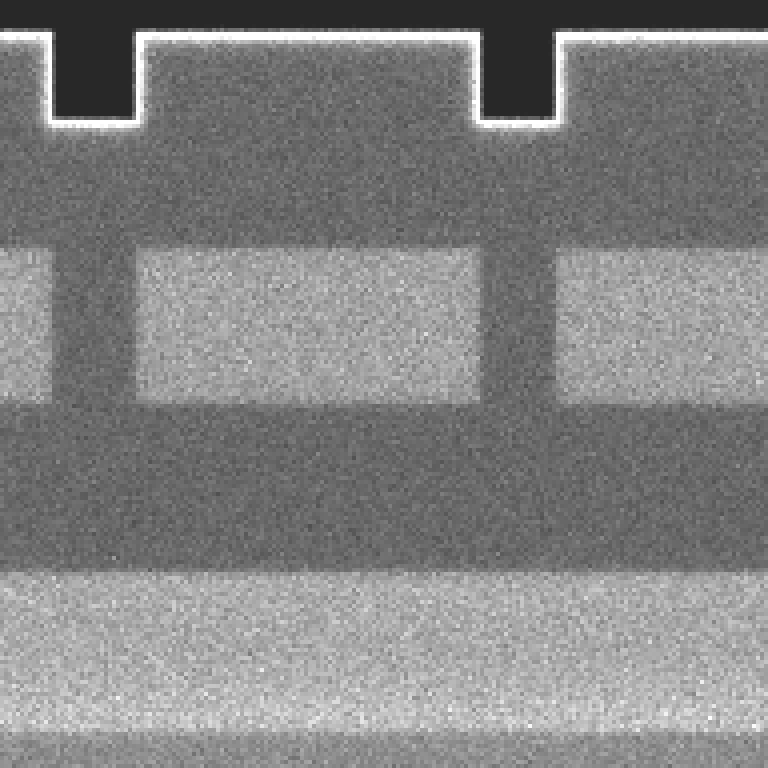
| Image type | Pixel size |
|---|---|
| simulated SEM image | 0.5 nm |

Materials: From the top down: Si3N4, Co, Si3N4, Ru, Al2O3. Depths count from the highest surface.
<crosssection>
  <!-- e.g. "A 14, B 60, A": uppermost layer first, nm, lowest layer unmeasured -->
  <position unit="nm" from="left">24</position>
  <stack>Si3N4 108, Co 78, Si3N4 84, Ru 80, Al2O3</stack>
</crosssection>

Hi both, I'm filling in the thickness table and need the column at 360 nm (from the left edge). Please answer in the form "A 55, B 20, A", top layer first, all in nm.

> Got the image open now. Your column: Si3N4 108, Co 78, Si3N4 84, Ru 80, Al2O3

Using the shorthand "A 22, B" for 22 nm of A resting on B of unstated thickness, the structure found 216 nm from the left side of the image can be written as Si3N4 108, Co 78, Si3N4 84, Ru 80, Al2O3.